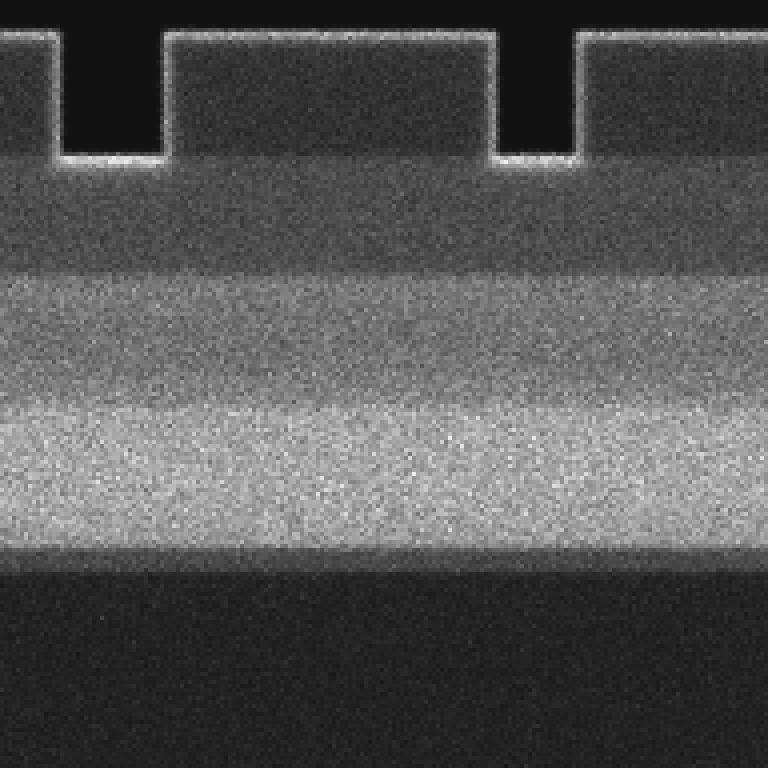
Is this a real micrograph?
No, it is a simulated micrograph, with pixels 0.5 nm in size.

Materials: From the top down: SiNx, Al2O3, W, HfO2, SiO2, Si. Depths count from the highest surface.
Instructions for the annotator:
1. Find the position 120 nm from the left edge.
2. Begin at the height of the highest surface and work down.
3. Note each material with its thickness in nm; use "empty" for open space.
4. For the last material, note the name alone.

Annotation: SiNx 62, Al2O3 60, W 66, HfO2 70, SiO2 12, Si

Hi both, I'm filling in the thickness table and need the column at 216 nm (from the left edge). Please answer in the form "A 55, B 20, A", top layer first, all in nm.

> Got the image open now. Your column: SiNx 62, Al2O3 60, W 66, HfO2 70, SiO2 12, Si